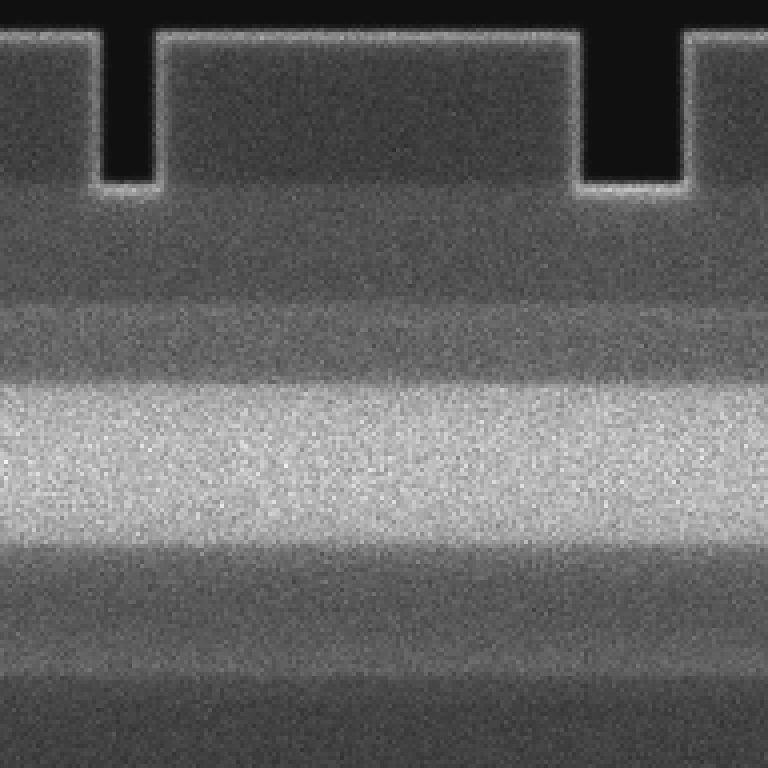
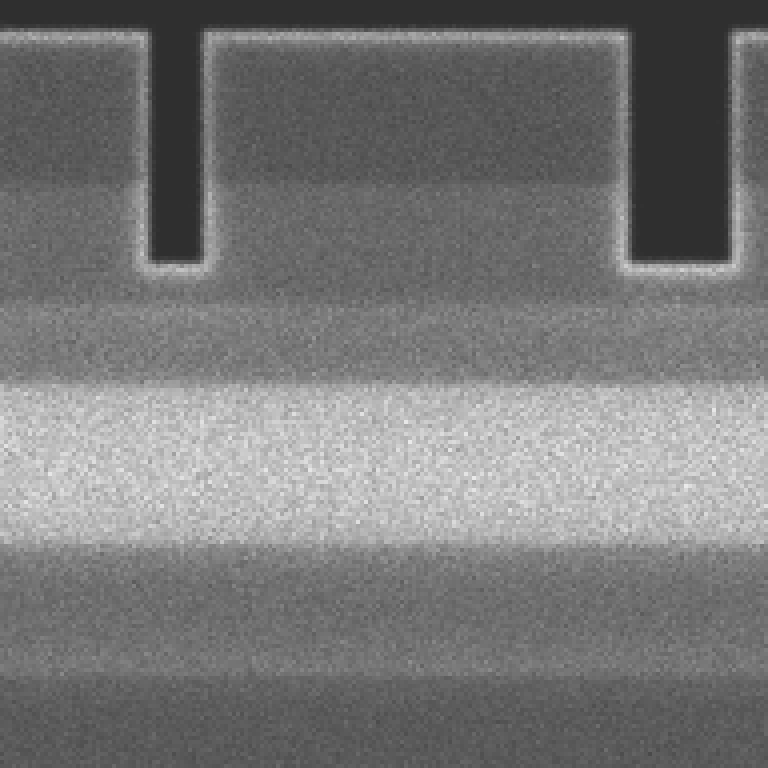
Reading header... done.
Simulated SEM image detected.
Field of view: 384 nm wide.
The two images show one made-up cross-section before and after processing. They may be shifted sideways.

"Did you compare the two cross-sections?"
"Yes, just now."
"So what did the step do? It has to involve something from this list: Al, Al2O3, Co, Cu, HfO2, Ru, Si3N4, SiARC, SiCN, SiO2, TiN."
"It removed Al2O3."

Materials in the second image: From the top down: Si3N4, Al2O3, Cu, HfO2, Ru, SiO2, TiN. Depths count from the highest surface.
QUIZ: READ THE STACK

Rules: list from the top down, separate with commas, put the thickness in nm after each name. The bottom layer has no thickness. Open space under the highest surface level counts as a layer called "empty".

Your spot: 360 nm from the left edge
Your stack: empty 116, Al2O3 20, Cu 40, HfO2 80, Ru 66, SiO2 12, TiN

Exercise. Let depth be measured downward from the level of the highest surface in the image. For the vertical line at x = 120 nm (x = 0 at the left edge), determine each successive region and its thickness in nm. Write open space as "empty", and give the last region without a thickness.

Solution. Si3N4 76, Al2O3 60, Cu 40, HfO2 80, Ru 66, SiO2 12, TiN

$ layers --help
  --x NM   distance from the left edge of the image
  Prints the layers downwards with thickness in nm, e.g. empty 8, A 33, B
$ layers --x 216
Si3N4 76, Al2O3 60, Cu 40, HfO2 80, Ru 66, SiO2 12, TiN